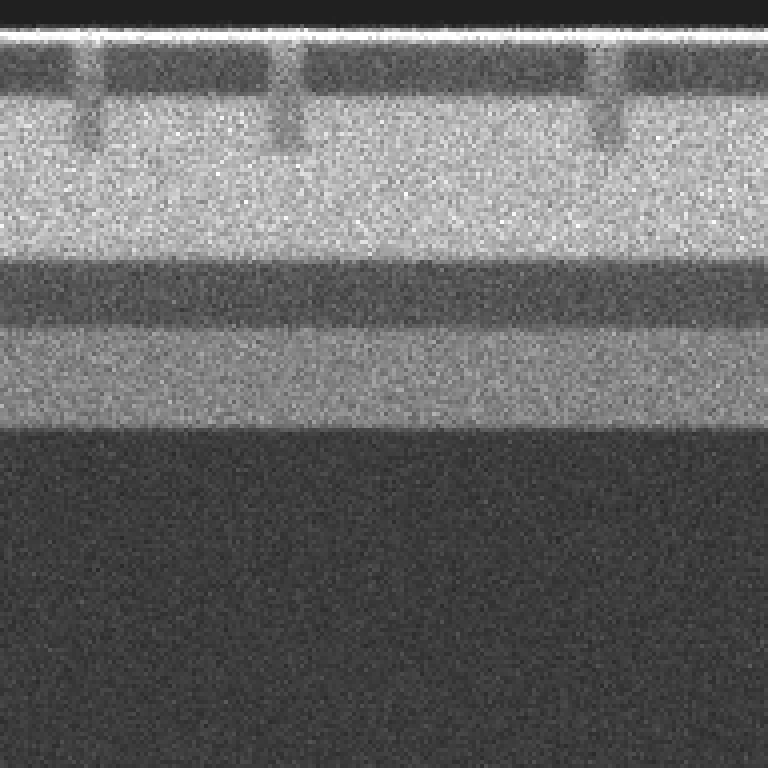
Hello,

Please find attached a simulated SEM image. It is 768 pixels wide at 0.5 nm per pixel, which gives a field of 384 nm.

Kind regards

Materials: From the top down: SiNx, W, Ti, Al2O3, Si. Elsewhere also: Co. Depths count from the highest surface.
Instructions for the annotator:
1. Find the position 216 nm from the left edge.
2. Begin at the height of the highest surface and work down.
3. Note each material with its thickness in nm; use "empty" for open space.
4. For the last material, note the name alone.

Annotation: SiNx 32, W 82, Ti 34, Al2O3 50, Si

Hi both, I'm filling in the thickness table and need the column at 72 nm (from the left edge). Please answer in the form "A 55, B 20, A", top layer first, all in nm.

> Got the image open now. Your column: SiNx 32, W 82, Ti 34, Al2O3 50, Si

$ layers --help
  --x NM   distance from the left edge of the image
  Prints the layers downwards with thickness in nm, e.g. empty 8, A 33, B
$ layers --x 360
SiNx 32, W 82, Ti 34, Al2O3 50, Si